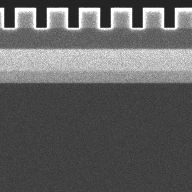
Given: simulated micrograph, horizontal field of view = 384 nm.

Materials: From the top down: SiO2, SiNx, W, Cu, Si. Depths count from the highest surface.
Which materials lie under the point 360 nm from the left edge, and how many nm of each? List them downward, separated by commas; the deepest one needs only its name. SiO2 40, SiNx 42, W 44, Cu 24, Si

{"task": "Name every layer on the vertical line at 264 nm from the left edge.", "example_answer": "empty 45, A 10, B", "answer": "empty 40, SiNx 42, W 44, Cu 24, Si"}